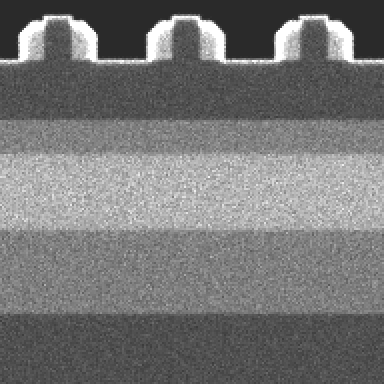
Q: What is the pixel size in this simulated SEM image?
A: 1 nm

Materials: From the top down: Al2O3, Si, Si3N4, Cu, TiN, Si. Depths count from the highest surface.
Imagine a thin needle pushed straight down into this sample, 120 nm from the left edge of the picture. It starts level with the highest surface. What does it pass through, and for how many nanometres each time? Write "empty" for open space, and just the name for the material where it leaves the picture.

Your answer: empty 44, Si 60, Si3N4 34, Cu 76, TiN 84, Si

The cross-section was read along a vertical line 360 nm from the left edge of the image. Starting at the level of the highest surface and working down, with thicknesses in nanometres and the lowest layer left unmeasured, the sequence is empty 44, Si 60, Si3N4 34, Cu 76, TiN 84, Si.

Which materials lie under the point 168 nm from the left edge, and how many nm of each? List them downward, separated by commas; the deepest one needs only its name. empty 6, Al2O3 38, Si 60, Si3N4 34, Cu 76, TiN 84, Si